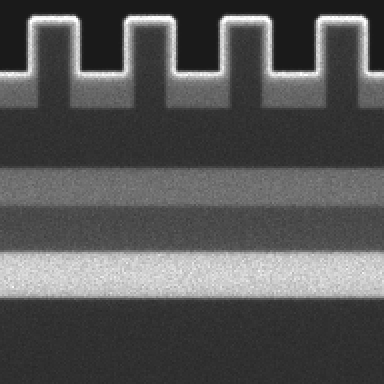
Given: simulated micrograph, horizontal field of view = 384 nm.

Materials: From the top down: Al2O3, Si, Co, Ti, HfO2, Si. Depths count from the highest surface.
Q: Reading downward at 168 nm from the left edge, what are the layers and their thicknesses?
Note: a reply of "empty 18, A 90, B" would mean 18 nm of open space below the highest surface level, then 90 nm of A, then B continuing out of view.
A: Al2O3 92, Si 60, Co 38, Ti 46, HfO2 46, Si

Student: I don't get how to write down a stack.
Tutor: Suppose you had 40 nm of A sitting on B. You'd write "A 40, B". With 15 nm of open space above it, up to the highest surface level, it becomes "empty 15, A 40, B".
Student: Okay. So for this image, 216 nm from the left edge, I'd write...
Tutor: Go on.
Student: empty 56, Al2O3 36, Si 60, Co 38, Ti 46, HfO2 46, Si